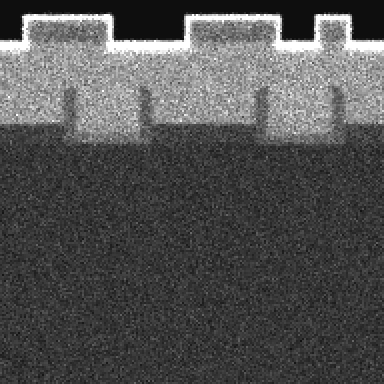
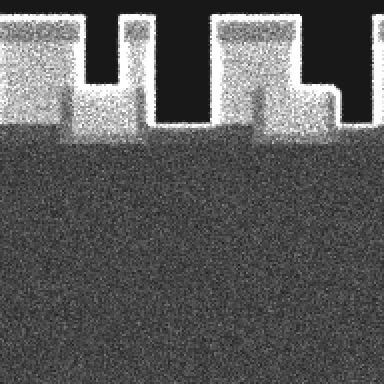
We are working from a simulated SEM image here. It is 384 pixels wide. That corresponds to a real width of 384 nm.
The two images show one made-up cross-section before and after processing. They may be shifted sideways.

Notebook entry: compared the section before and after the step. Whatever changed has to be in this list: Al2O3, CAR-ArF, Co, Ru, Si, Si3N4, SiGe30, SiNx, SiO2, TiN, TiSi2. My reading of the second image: SiO2 removed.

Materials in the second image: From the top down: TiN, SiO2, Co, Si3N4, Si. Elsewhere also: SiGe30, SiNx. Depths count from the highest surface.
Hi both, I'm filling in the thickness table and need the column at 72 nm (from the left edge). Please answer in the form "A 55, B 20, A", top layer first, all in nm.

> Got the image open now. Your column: TiN 26, SiO2 44, Co 48, Si3N4 10, Si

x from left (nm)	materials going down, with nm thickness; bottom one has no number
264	TiN 26, SiO2 44, Co 48, Si3N4 10, Si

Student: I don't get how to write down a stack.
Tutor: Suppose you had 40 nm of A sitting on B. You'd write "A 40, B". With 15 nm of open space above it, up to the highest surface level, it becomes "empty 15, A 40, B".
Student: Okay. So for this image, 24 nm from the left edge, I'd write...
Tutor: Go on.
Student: TiN 26, SiO2 82, SiGe30 20, Si